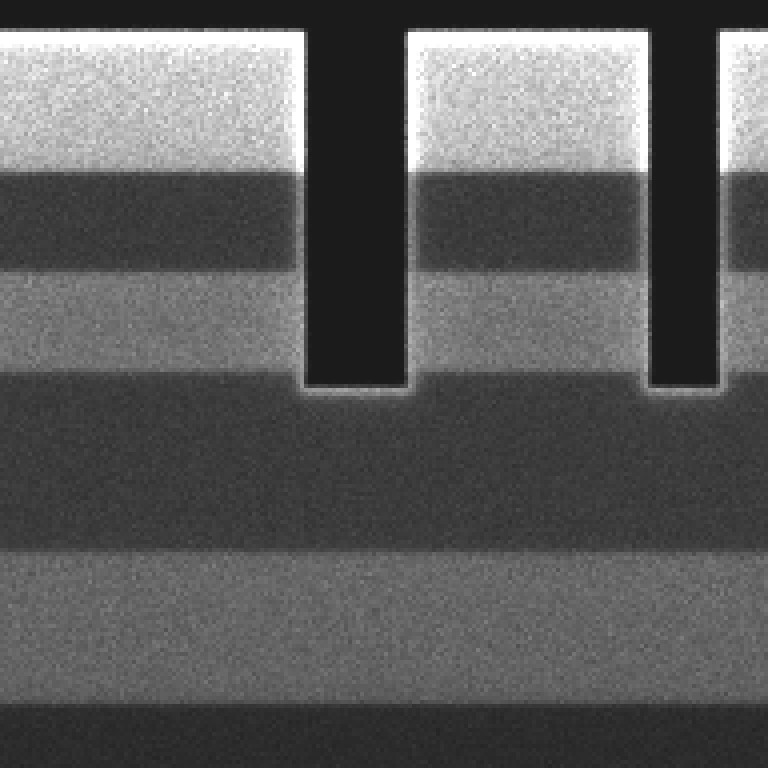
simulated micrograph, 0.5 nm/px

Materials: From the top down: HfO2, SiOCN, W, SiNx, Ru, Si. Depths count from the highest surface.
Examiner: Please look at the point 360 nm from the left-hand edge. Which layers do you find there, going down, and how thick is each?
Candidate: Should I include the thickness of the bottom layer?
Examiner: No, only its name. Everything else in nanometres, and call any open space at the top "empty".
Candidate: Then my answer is HfO2 70, SiOCN 50, W 50, SiNx 90, Ru 76, Si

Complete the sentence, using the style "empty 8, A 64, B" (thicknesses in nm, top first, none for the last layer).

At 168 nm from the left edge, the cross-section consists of empty 178, SiNx 82, Ru 76, Si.